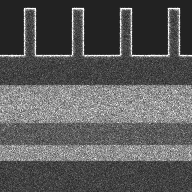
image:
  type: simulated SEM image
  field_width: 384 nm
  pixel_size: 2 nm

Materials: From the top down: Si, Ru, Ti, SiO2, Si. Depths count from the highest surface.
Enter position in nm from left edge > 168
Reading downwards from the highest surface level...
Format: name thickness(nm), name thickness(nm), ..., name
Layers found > empty 94, Si 60, Ru 76, Ti 44, SiO2 32, Si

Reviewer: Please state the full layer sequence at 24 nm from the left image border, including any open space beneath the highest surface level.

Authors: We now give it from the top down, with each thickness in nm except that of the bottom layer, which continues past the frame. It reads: empty 94, Si 60, Ru 76, Ti 44, SiO2 32, Si